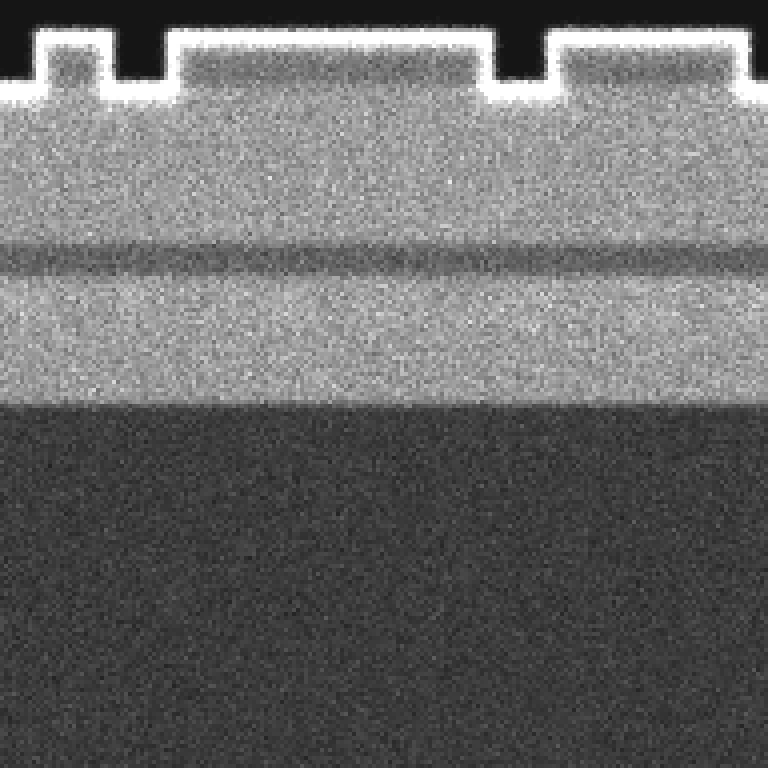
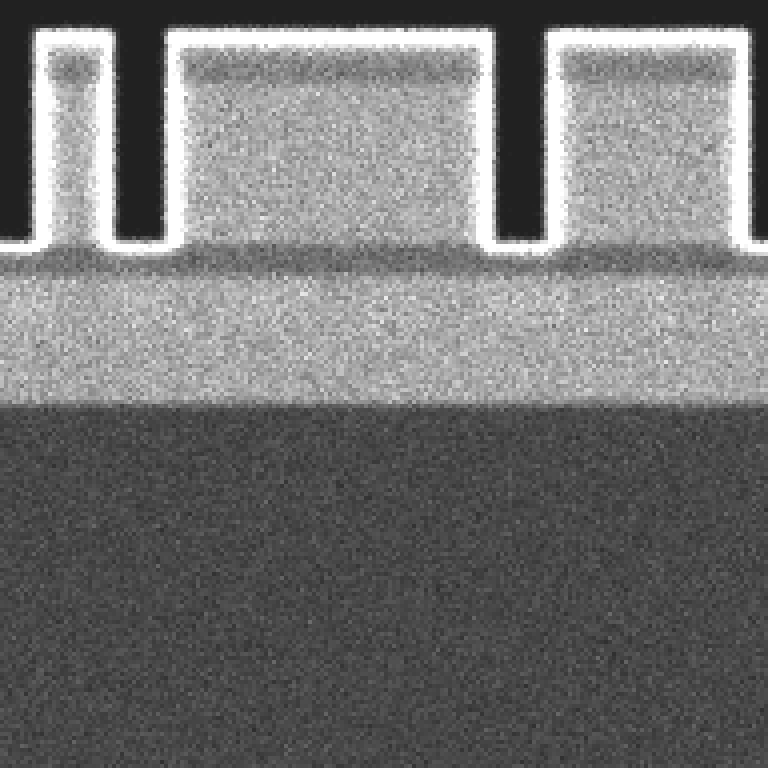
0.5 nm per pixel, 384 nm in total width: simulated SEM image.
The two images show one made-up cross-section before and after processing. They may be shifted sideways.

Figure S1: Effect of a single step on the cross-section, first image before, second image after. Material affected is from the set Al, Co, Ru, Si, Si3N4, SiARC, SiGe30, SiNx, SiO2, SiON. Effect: removed SiO2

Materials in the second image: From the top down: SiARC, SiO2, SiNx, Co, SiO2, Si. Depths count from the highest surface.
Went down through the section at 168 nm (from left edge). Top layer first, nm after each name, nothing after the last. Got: SiARC 26, SiO2 80, SiNx 16, SiO2 64, Si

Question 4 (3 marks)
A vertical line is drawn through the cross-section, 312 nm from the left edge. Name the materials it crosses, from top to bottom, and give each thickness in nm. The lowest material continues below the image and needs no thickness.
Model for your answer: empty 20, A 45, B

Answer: SiARC 26, SiO2 80, SiNx 16, Co 24, SiO2 40, Si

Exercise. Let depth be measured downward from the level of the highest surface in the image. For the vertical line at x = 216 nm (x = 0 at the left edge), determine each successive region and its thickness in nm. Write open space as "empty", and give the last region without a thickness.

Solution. SiARC 26, SiO2 80, SiNx 16, SiO2 64, Si